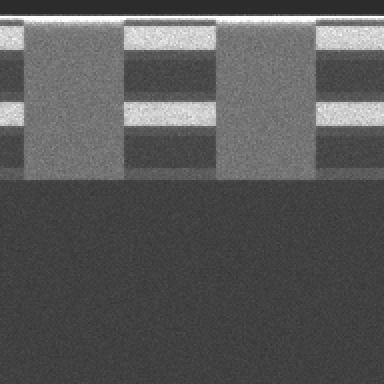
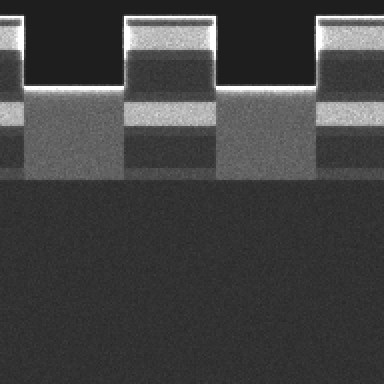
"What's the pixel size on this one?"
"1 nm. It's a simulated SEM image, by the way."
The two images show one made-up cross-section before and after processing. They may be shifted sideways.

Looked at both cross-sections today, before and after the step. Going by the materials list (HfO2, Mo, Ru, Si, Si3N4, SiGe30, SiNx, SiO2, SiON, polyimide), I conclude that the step removed SiO2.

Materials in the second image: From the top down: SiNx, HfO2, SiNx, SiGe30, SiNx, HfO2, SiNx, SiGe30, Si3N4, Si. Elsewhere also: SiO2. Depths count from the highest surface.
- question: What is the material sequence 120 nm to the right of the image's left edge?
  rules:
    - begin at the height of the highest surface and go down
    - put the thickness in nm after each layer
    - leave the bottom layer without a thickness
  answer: empty 70, SiO2 94, Si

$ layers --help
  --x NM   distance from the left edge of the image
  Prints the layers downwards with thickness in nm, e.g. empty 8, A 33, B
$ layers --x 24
empty 70, SiO2 94, Si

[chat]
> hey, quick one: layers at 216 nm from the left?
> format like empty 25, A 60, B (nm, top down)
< empty 70, SiO2 94, Si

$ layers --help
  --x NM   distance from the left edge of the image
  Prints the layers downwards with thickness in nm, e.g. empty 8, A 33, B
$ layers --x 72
empty 70, SiO2 94, Si